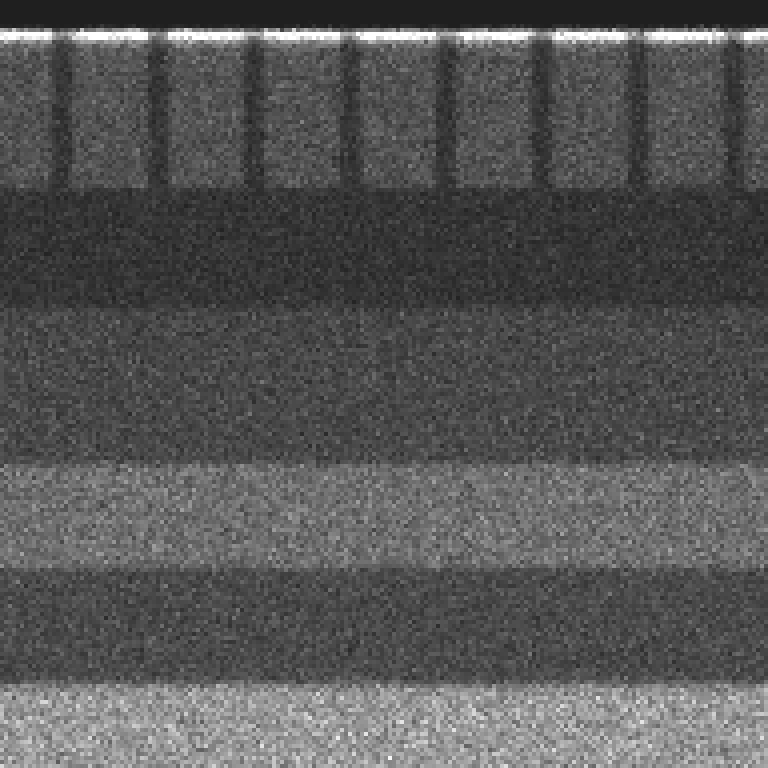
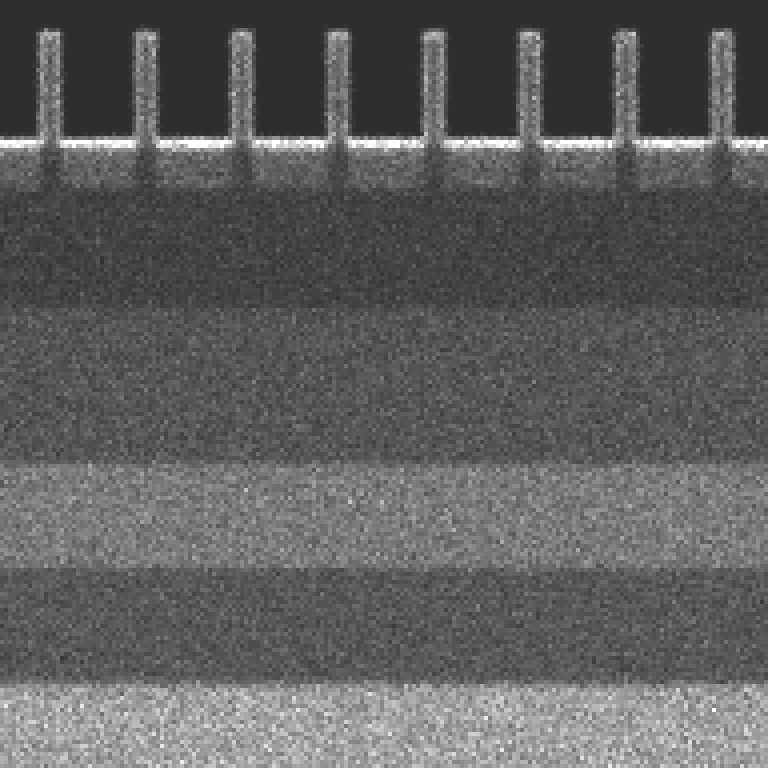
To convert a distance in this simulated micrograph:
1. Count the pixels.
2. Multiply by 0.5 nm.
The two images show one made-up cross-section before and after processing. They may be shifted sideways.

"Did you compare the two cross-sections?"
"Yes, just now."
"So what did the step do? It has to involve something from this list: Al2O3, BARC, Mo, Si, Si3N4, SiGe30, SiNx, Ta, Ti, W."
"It removed Si3N4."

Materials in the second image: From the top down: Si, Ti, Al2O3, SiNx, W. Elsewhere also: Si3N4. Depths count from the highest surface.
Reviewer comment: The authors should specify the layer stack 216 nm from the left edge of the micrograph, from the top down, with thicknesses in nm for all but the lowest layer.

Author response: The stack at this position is Si 138, Ti 78, Al2O3 52, SiNx 58, W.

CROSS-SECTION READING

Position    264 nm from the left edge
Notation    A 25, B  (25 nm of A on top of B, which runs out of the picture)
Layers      Si 138, Ti 78, Al2O3 52, SiNx 58, W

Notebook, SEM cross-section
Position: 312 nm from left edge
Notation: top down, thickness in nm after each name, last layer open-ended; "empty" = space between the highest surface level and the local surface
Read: Si 138, Ti 78, Al2O3 52, SiNx 58, W